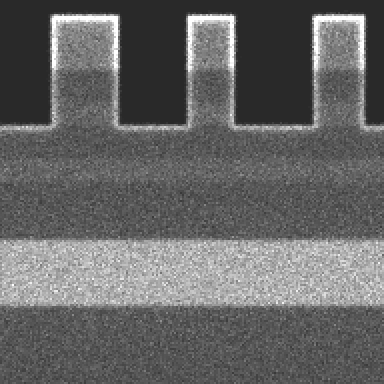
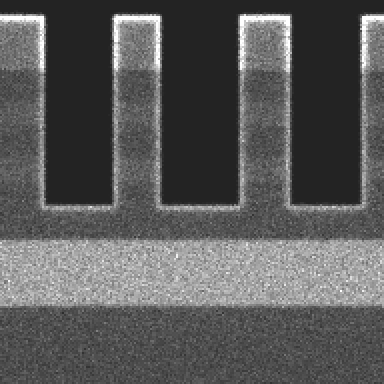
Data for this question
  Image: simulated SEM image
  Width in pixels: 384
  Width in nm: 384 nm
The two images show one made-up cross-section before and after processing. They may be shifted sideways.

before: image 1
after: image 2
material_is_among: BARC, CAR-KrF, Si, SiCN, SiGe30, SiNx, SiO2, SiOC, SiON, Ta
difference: Si and SiGe30, removed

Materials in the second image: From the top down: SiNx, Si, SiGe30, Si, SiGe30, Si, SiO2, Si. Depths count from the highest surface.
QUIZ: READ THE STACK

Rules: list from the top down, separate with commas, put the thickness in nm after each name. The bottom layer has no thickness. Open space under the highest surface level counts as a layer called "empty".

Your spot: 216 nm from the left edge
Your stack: empty 190, Si 34, SiO2 66, Si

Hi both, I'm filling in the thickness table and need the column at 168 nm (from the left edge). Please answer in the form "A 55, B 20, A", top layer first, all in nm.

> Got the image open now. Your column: empty 190, Si 34, SiO2 66, Si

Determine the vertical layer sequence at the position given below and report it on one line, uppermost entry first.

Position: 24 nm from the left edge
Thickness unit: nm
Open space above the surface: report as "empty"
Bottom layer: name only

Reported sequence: SiNx 54, Si 32, SiGe30 24, Si 32, SiGe30 24, Si 58, SiO2 66, Si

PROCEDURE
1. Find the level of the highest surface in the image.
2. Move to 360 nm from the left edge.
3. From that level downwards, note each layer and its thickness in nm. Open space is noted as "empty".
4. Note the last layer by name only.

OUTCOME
empty 190, Si 34, SiO2 66, Si